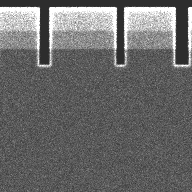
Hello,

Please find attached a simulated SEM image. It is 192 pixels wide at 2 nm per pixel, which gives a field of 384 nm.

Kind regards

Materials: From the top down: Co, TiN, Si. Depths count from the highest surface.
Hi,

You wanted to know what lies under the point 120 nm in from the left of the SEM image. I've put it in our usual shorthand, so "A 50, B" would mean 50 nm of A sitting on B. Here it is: Co 46, TiN 36, Si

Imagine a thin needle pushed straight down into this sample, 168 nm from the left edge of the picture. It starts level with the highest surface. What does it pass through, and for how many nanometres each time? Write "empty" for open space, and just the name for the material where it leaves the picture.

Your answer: Co 46, TiN 36, Si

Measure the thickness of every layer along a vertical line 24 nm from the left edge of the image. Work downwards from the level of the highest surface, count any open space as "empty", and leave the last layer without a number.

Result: Co 46, TiN 36, Si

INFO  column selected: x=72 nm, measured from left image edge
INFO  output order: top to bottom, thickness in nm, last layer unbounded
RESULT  Co 46, TiN 36, Si